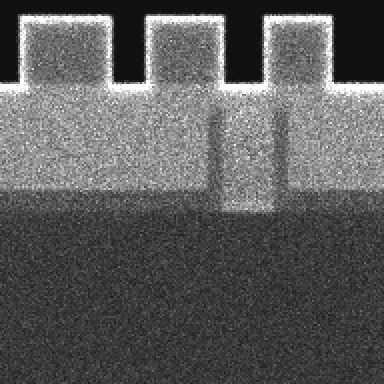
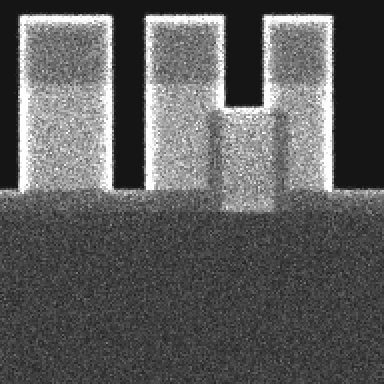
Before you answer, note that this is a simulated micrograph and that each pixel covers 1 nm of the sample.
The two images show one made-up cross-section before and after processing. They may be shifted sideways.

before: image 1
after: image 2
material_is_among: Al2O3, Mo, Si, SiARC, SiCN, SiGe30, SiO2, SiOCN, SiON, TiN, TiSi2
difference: SiO2, removed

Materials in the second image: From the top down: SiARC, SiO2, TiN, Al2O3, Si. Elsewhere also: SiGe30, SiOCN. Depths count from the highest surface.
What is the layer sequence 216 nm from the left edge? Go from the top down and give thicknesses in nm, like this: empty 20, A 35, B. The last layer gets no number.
SiARC 68, SiO2 24, SiOCN 104, Si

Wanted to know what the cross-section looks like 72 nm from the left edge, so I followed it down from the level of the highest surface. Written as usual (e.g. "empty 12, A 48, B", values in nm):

SiARC 68, SiO2 106, SiGe30 22, Si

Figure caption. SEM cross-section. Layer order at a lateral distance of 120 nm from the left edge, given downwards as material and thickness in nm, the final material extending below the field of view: empty 174, SiGe30 22, Si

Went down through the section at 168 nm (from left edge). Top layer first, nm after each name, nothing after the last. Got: SiARC 68, SiO2 106, SiGe30 22, Si